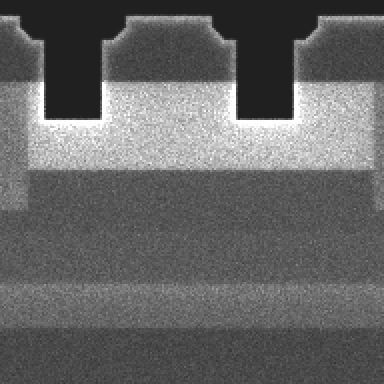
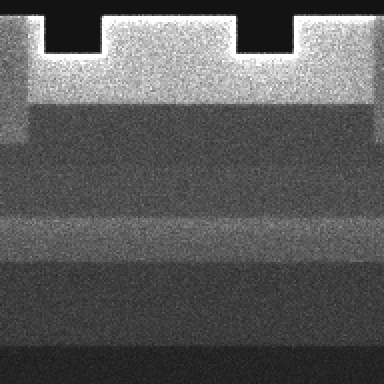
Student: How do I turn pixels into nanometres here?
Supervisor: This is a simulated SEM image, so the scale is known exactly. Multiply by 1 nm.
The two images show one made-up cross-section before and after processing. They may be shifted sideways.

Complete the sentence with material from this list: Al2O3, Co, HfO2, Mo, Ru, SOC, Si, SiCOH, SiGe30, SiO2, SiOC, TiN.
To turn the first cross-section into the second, SOC must be removed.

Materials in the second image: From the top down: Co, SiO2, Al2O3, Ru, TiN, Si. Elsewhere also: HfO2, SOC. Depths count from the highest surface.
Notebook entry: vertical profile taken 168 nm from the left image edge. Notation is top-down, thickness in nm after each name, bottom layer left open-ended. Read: HfO2 88, SiO2 62, Al2O3 52, Ru 44, TiN 84, Si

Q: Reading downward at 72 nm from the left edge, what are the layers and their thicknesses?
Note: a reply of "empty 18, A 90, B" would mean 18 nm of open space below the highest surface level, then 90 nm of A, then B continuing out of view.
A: empty 38, HfO2 50, SiO2 62, Al2O3 52, Ru 44, TiN 84, Si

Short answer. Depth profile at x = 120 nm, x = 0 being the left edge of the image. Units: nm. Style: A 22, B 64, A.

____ HfO2 88, SiO2 62, Al2O3 52, Ru 44, TiN 84, Si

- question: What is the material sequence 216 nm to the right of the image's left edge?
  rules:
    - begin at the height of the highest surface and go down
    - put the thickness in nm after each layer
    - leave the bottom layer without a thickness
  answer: HfO2 88, SiO2 62, Al2O3 52, Ru 44, TiN 84, Si